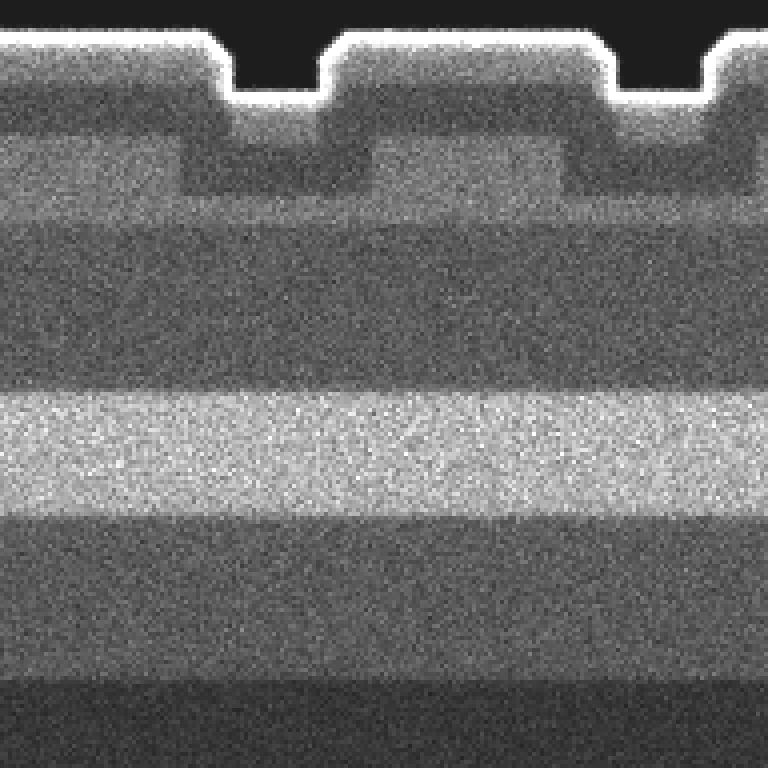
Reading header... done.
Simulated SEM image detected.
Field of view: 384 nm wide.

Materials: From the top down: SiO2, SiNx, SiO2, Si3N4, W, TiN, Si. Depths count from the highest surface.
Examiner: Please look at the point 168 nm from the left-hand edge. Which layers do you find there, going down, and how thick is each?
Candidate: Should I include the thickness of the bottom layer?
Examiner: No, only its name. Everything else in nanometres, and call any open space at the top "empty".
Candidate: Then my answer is empty 4, SiO2 26, SiNx 52, SiO2 14, Si3N4 84, W 62, TiN 82, Si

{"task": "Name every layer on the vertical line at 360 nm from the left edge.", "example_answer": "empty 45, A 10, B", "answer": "empty 4, SiO2 26, SiNx 52, SiO2 14, Si3N4 84, W 62, TiN 82, Si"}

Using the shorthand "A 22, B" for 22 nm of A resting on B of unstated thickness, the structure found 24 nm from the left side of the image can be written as SiO2 26, SiNx 26, SiO2 44, Si3N4 84, W 62, TiN 82, Si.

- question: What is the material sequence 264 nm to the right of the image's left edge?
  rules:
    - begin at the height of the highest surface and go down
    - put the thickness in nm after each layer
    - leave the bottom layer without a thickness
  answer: SiO2 26, SiNx 26, SiO2 44, Si3N4 84, W 62, TiN 82, Si